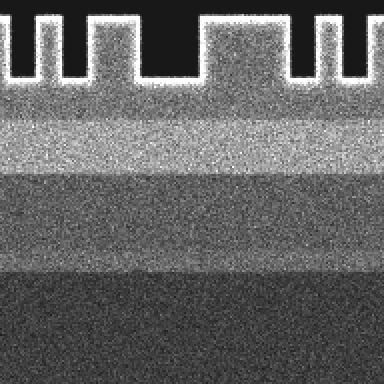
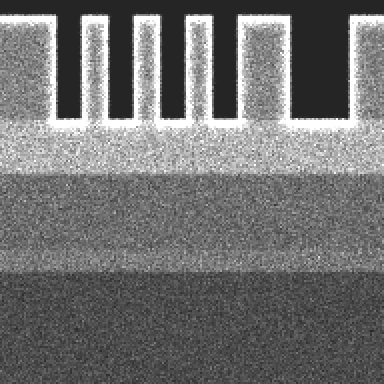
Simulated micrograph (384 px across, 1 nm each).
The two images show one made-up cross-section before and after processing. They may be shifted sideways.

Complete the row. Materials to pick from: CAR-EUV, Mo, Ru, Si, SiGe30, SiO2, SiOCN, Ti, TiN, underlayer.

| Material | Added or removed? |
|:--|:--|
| underlayer | removed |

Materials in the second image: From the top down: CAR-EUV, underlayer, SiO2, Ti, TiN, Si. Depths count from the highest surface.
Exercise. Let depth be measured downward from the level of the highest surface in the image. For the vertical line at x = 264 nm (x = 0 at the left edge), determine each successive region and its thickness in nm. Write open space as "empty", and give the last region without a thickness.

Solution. CAR-EUV 62, underlayer 42, SiO2 54, Ti 76, TiN 22, Si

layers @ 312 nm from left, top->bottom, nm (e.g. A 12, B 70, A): empty 104, SiO2 54, Ti 76, TiN 22, Si